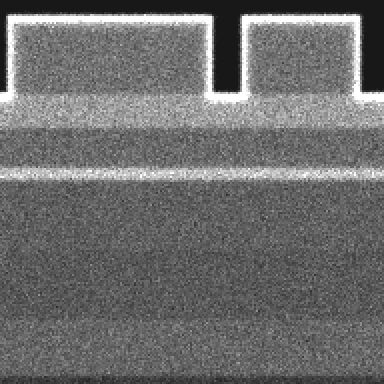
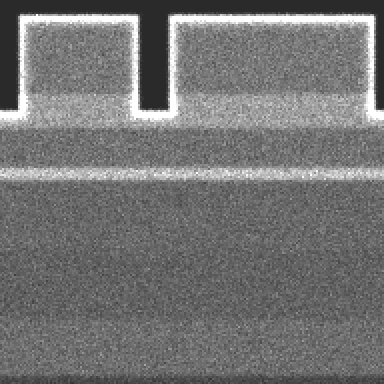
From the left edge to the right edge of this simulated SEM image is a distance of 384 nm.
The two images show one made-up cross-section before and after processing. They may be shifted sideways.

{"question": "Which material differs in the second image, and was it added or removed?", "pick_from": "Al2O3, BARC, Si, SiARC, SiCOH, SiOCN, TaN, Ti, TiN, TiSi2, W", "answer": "Al2O3, removed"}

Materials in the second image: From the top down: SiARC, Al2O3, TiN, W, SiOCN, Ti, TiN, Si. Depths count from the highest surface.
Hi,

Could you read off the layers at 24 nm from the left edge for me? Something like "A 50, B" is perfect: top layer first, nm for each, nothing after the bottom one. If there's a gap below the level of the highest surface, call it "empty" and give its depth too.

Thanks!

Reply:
SiARC 78, Al2O3 34, TiN 40, W 12, SiOCN 70, Ti 70, TiN 56, Si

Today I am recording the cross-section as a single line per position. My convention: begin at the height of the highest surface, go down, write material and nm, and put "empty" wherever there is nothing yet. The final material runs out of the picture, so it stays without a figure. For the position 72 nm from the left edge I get SiARC 78, Al2O3 34, TiN 40, W 12, SiOCN 70, Ti 70, TiN 56, Si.